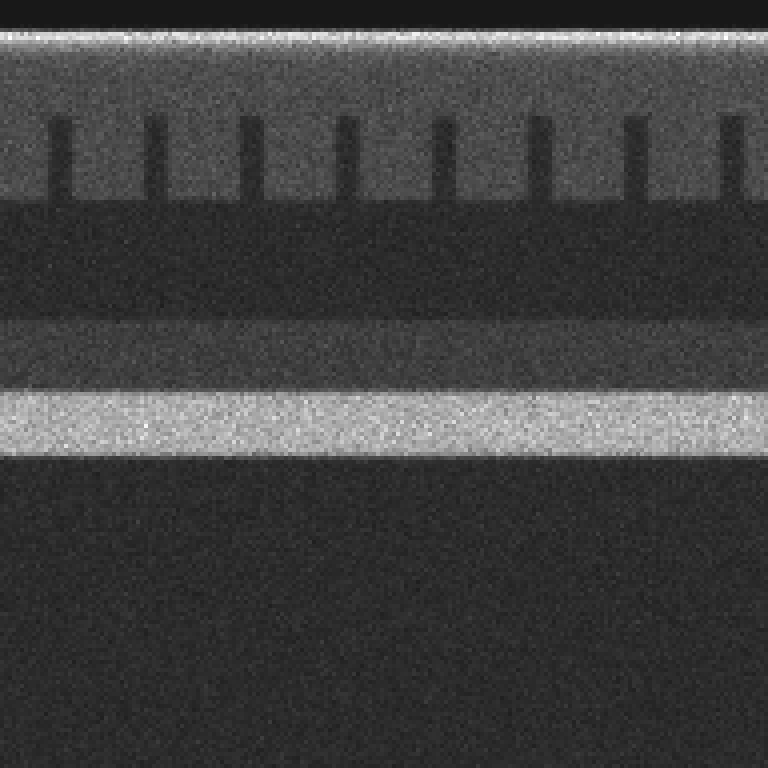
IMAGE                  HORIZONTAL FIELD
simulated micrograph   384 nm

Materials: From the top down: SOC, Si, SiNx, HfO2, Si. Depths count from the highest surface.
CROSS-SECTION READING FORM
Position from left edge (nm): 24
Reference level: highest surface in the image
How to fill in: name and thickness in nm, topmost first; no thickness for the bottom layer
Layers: SOC 42, Si 102, SiNx 36, HfO2 32, Si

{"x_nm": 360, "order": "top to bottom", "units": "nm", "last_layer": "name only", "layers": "SOC 42, Si 102, SiNx 36, HfO2 32, Si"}